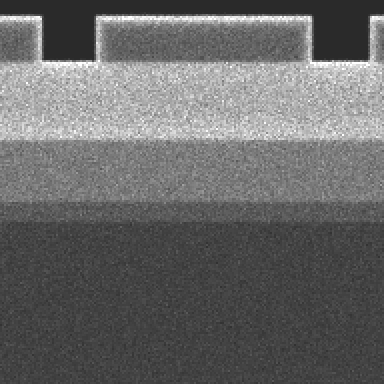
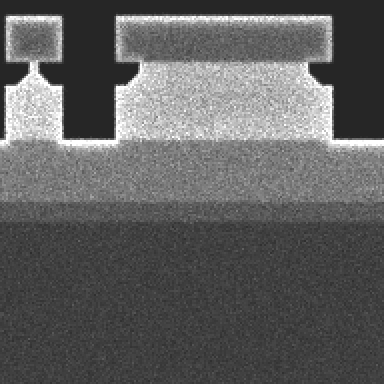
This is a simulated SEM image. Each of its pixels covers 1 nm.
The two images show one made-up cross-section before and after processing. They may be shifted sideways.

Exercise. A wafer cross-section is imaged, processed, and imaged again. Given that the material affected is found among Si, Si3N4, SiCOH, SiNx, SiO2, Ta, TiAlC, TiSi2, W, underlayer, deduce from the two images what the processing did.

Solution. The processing removed W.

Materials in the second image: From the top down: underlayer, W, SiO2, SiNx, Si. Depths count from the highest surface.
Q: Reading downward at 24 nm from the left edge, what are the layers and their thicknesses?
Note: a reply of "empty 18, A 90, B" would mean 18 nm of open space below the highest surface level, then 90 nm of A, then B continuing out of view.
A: underlayer 46, empty 16, W 62, SiO2 62, SiNx 20, Si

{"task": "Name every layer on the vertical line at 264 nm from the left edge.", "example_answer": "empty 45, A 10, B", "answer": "underlayer 46, W 78, SiO2 62, SiNx 20, Si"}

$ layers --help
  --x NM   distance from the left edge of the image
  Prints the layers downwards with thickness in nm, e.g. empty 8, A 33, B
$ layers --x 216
underlayer 46, W 78, SiO2 62, SiNx 20, Si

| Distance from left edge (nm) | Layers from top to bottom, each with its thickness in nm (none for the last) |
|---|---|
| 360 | empty 124, SiO2 62, SiNx 20, Si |